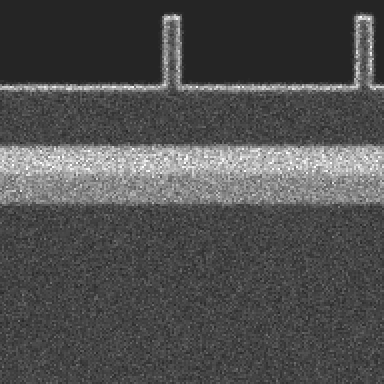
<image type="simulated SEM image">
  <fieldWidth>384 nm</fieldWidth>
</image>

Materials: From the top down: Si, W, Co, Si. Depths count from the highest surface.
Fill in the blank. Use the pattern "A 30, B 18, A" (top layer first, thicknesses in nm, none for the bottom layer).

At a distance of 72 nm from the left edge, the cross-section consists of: empty 70, Si 60, W 28, Co 30, Si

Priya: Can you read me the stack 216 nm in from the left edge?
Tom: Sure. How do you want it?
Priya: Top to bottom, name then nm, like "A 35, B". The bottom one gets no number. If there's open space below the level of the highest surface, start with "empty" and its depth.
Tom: empty 70, Si 60, W 28, Co 30, Si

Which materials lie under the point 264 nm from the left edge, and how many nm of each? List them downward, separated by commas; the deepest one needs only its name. empty 70, Si 60, W 28, Co 30, Si